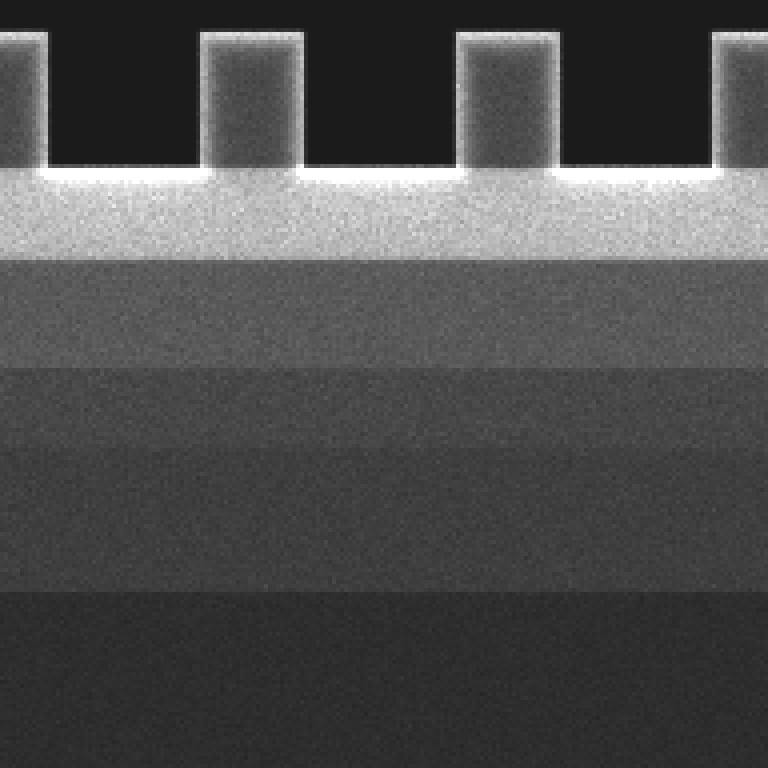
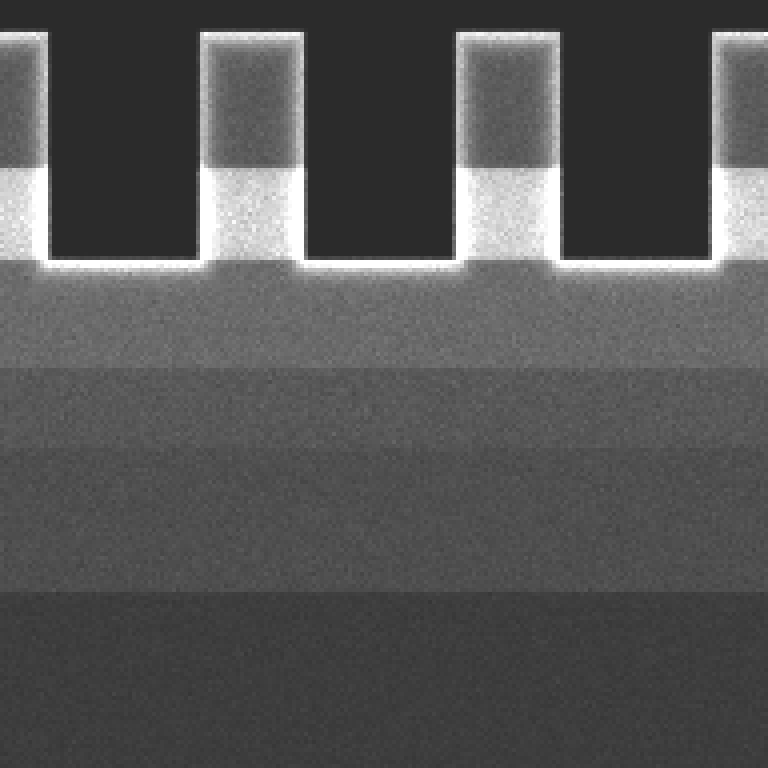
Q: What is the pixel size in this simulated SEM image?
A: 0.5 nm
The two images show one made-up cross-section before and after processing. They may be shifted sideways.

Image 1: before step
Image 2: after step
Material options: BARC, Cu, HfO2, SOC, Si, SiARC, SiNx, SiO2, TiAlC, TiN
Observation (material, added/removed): HfO2, removed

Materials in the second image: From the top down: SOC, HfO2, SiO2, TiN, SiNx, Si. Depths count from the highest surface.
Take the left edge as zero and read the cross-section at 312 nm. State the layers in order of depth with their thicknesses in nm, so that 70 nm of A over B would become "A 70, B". empty 114, SiO2 54, TiN 40, SiNx 72, Si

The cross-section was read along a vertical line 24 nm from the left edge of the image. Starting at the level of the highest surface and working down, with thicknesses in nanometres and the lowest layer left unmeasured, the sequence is empty 114, SiO2 54, TiN 40, SiNx 72, Si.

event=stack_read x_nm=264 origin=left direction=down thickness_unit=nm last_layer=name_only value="SOC 68, HfO2 46, SiO2 54, TiN 40, SiNx 72, Si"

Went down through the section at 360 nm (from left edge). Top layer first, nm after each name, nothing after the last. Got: SOC 68, HfO2 46, SiO2 54, TiN 40, SiNx 72, Si